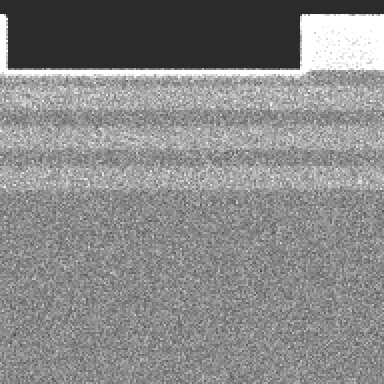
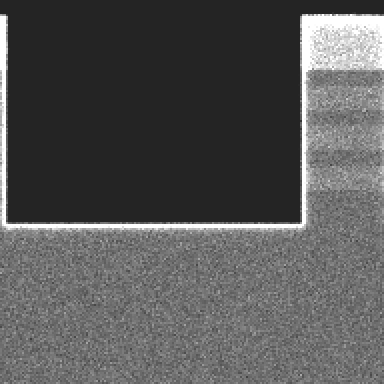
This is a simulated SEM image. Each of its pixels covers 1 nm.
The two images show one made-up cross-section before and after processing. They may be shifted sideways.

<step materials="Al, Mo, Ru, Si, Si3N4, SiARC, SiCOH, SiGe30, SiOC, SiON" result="removed Si and SiGe30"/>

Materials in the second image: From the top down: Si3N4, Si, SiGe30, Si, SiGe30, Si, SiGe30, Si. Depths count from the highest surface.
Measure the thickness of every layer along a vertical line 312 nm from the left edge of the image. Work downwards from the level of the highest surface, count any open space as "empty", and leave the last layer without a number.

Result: Si3N4 54, Si 16, SiGe30 24, Si 16, SiGe30 24, Si 16, SiGe30 24, Si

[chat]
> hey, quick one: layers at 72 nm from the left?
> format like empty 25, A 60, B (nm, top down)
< empty 208, Si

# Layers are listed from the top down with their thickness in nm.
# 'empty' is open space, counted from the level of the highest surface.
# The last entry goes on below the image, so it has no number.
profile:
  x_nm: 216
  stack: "empty 208, Si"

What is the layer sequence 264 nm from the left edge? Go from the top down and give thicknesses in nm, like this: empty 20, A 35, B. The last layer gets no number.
empty 208, Si